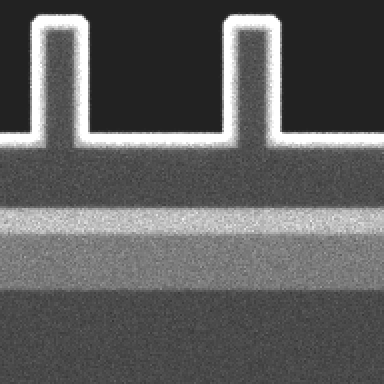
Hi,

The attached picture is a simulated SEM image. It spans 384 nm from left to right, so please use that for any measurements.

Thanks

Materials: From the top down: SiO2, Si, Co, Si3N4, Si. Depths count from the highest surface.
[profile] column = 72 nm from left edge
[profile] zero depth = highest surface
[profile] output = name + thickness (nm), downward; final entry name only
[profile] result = SiO2 14, Si 178, Co 26, Si3N4 56, Si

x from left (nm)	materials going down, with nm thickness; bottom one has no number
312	empty 118, SiO2 14, Si 60, Co 26, Si3N4 56, Si